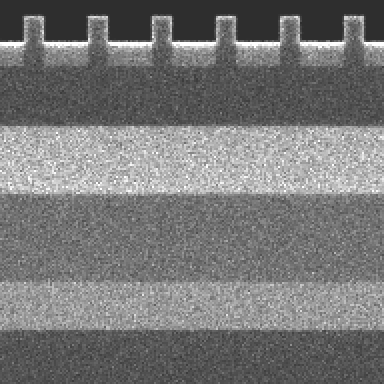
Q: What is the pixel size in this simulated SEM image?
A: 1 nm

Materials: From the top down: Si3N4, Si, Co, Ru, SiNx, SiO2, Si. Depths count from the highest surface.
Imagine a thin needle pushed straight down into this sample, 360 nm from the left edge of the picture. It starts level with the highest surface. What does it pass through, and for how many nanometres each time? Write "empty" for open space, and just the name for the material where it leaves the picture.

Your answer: Si 110, Co 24, Ru 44, SiNx 88, SiO2 48, Si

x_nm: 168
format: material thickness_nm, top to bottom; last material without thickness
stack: Si 110, Co 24, Ru 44, SiNx 88, SiO2 48, Si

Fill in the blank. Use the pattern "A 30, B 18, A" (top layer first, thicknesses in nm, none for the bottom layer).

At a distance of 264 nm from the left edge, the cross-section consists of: empty 26, Si3N4 24, Si 60, Co 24, Ru 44, SiNx 88, SiO2 48, Si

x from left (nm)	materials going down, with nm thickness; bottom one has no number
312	empty 26, Si3N4 24, Si 60, Co 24, Ru 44, SiNx 88, SiO2 48, Si